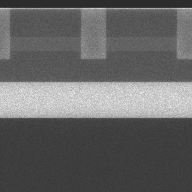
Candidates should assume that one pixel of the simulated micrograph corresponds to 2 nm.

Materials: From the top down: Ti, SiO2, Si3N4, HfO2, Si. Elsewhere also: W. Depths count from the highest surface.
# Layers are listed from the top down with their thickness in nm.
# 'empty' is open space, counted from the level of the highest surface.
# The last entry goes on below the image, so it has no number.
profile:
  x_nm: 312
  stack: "Ti 58, SiO2 28, Si3N4 62, HfO2 72, Si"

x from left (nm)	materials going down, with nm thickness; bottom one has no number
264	Ti 58, SiO2 28, Si3N4 62, HfO2 72, Si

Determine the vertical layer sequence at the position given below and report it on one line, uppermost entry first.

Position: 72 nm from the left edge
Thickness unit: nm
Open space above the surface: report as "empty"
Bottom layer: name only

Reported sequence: Ti 58, SiO2 28, Si3N4 62, HfO2 72, Si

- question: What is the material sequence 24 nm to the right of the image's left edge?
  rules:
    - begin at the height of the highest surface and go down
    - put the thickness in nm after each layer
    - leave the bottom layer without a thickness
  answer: Ti 58, SiO2 28, Si3N4 62, HfO2 72, Si